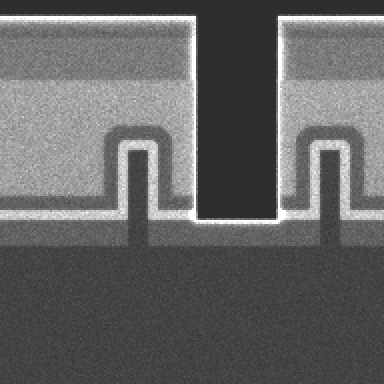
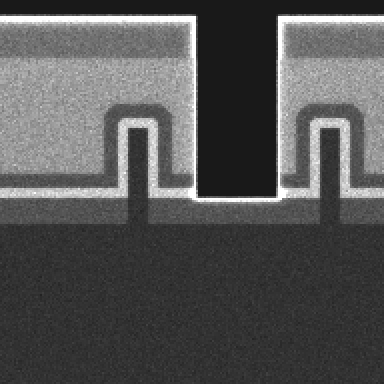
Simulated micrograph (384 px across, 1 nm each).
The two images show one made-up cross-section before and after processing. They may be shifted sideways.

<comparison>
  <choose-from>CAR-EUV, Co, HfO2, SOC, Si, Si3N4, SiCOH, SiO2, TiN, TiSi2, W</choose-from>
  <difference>SOC removed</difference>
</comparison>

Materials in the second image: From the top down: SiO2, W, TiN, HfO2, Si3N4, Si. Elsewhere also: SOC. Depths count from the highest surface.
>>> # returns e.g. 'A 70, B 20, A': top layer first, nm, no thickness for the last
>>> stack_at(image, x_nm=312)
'SiO2 42, W 46, TiN 16, HfO2 78, Si3N4 26, Si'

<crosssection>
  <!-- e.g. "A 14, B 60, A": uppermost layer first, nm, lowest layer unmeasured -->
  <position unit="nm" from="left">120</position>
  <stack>SiO2 42, W 46, TiN 16, HfO2 78, Si3N4 26, Si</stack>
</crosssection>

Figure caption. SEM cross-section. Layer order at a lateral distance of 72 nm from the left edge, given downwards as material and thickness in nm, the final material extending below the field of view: SiO2 42, W 116, TiN 14, HfO2 10, Si3N4 26, Si